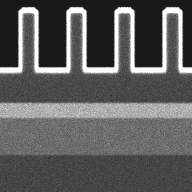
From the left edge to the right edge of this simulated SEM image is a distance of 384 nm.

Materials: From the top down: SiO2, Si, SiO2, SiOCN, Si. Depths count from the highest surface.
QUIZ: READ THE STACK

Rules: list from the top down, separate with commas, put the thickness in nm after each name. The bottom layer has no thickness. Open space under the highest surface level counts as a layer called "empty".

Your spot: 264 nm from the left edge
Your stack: empty 4, SiO2 126, Si 60, SiO2 30, SiOCN 74, Si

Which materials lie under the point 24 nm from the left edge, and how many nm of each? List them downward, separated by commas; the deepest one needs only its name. empty 120, SiO2 10, Si 60, SiO2 30, SiOCN 74, Si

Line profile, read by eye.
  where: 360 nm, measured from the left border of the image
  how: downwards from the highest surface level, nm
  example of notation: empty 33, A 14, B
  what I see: empty 4, SiO2 126, Si 60, SiO2 30, SiOCN 74, Si